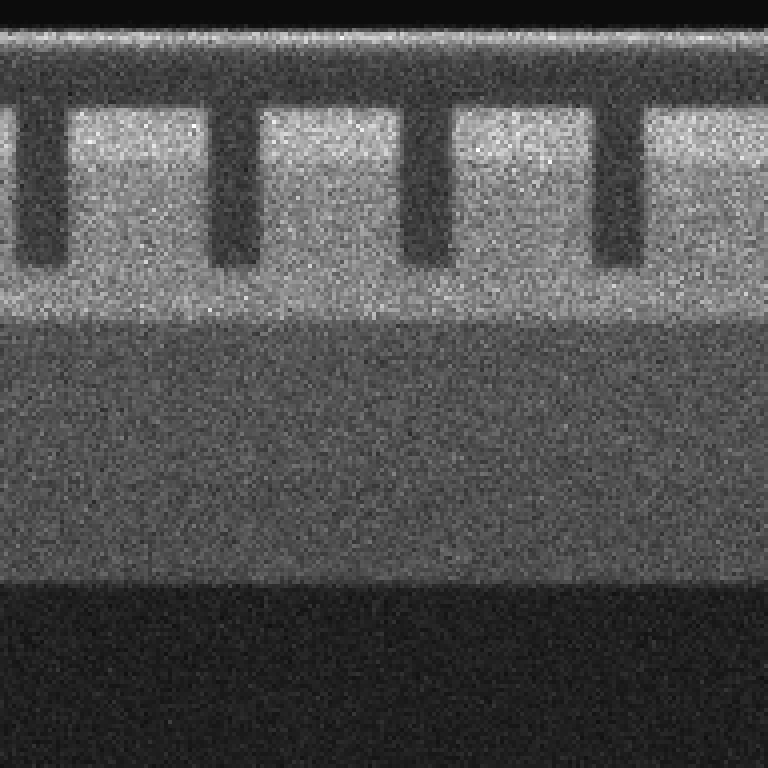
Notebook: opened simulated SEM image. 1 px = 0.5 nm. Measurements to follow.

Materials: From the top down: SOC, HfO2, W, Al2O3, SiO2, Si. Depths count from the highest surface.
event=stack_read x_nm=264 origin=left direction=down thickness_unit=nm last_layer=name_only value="SOC 38, HfO2 26, W 80, Al2O3 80, SiO2 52, Si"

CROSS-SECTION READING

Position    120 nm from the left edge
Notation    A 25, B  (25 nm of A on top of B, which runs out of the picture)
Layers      SOC 118, W 26, Al2O3 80, SiO2 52, Si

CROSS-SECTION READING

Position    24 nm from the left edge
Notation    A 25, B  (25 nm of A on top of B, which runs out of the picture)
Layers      SOC 118, W 26, Al2O3 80, SiO2 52, Si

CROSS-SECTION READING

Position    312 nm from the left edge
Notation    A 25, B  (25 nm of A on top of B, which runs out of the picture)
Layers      SOC 118, W 26, Al2O3 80, SiO2 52, Si